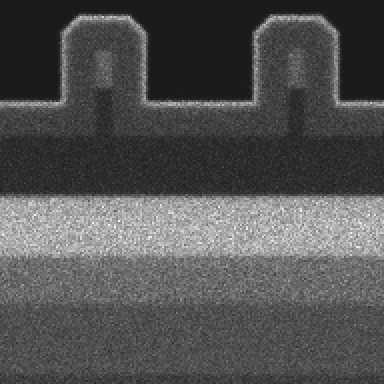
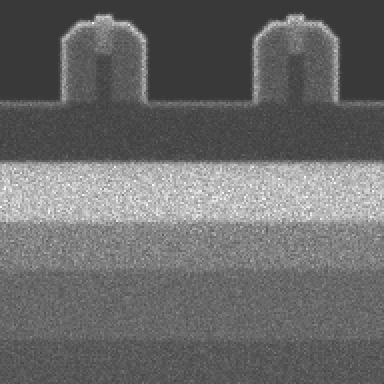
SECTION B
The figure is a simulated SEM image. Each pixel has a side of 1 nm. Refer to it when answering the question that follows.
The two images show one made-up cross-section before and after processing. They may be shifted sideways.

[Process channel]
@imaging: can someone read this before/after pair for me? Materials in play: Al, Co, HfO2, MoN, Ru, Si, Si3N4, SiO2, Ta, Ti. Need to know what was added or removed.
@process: Si3N4 removed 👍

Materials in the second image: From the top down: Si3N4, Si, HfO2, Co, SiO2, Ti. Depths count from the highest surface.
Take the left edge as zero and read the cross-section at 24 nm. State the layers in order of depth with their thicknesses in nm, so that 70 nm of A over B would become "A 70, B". empty 86, Si 60, HfO2 60, Co 48, SiO2 70, Ti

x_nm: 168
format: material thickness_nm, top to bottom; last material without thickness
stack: empty 86, Si 60, HfO2 60, Co 48, SiO2 70, Ti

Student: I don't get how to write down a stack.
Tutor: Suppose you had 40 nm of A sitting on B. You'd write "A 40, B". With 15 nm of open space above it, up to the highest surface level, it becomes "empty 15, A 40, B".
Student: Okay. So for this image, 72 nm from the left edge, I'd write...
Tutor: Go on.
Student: empty 12, Si3N4 74, Si 60, HfO2 60, Co 48, SiO2 70, Ti